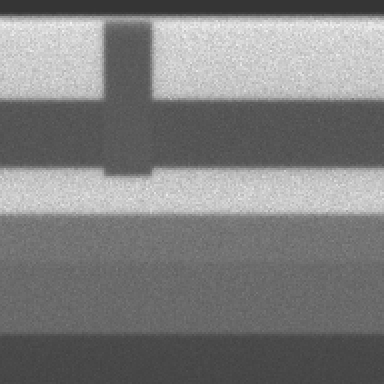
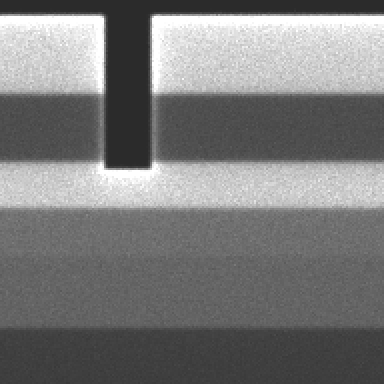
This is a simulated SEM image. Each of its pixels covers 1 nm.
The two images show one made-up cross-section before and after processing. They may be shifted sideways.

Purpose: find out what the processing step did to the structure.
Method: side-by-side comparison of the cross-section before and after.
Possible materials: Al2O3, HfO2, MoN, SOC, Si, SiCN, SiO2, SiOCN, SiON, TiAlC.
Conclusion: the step removed SOC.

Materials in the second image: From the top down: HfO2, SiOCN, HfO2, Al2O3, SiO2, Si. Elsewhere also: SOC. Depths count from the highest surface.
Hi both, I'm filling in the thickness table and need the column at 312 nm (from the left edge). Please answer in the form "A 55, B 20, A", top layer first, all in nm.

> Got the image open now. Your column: HfO2 78, SiOCN 68, HfO2 46, Al2O3 48, SiO2 72, Si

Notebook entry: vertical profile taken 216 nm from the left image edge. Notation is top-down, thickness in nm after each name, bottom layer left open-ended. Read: HfO2 78, SiOCN 68, HfO2 46, Al2O3 48, SiO2 72, Si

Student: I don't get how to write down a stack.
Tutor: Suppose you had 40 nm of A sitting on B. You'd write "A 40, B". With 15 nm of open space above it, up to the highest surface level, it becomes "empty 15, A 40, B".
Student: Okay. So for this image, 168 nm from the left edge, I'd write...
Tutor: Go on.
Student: HfO2 78, SiOCN 68, HfO2 46, Al2O3 48, SiO2 72, Si